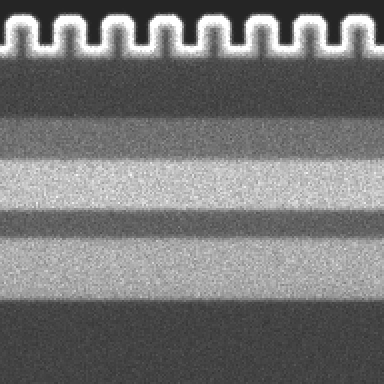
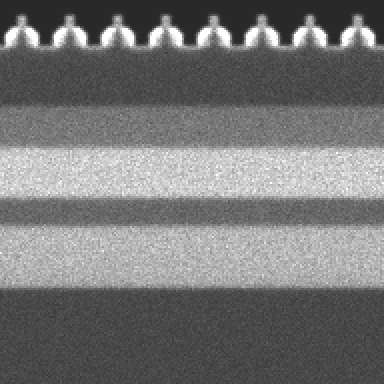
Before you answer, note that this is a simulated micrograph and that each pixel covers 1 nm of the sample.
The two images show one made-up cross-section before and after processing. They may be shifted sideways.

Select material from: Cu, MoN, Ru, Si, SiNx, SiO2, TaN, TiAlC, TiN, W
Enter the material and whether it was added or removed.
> SiO2 / removed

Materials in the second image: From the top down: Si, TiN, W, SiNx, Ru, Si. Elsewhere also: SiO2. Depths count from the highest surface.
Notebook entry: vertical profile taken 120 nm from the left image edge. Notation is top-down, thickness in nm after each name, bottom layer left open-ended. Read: Si 90, TiN 42, W 50, SiNx 28, Ru 62, Si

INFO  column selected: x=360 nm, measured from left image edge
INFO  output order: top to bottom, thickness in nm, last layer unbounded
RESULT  Si 90, TiN 42, W 50, SiNx 28, Ru 62, Si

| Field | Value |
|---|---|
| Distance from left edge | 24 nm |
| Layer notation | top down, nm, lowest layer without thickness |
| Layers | Si 90, TiN 42, W 50, SiNx 28, Ru 62, Si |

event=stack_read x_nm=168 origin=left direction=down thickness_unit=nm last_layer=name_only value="Si 90, TiN 42, W 50, SiNx 28, Ru 62, Si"